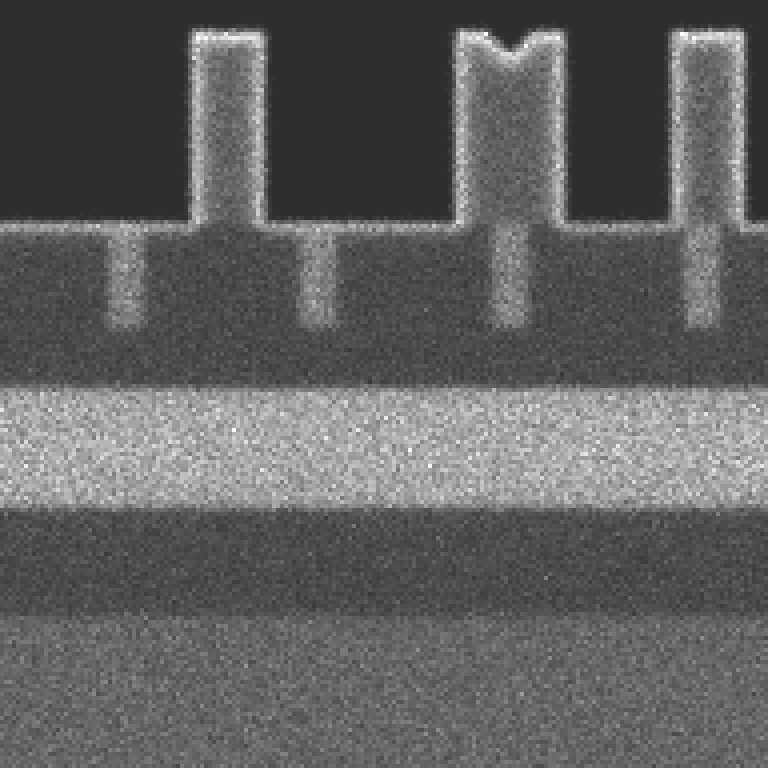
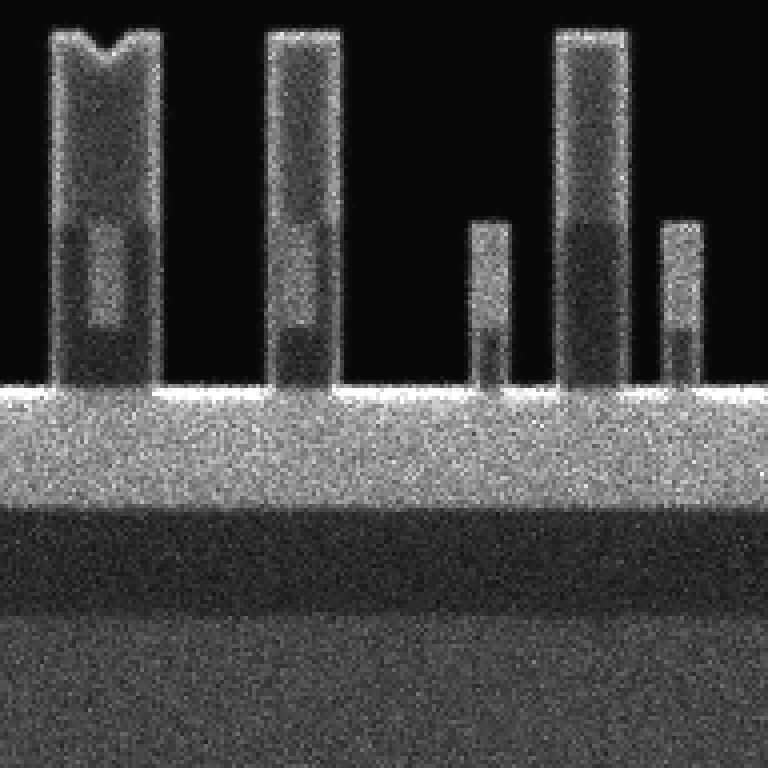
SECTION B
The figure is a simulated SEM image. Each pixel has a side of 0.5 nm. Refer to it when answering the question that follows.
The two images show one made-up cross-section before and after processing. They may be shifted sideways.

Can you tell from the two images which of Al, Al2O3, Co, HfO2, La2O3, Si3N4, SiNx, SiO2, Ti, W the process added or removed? Yes, it removed SiNx.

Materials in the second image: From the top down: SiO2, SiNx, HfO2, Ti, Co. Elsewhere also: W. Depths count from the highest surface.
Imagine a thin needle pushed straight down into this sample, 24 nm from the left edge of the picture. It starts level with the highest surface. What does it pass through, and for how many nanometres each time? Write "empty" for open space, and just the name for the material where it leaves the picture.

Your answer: empty 178, HfO2 60, Ti 54, Co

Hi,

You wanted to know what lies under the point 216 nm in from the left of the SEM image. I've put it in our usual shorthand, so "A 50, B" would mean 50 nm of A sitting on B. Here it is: empty 178, HfO2 60, Ti 54, Co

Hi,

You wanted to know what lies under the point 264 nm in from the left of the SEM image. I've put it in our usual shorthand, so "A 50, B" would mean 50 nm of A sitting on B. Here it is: empty 178, HfO2 60, Ti 54, Co